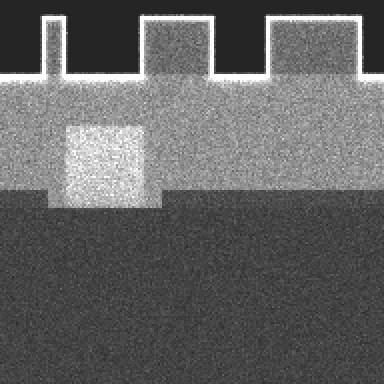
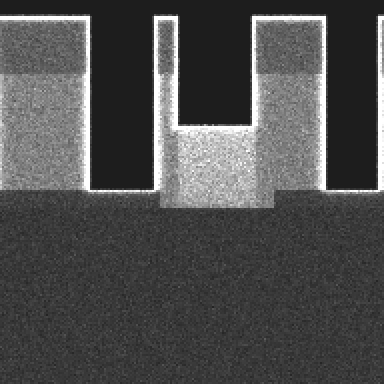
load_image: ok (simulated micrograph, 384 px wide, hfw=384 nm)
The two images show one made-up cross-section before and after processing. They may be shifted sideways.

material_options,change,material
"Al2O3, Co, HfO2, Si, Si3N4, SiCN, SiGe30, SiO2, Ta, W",removed,SiO2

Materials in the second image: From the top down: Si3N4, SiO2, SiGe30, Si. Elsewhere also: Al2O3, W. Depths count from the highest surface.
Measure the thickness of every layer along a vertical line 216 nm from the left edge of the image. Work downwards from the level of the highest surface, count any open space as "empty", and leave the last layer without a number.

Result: empty 110, W 82, Si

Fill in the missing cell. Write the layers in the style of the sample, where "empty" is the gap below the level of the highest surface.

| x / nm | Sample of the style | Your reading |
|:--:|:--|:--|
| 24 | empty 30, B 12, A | Si3N4 58, SiO2 116, SiGe30 18, Si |